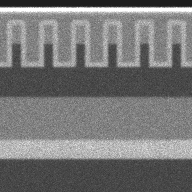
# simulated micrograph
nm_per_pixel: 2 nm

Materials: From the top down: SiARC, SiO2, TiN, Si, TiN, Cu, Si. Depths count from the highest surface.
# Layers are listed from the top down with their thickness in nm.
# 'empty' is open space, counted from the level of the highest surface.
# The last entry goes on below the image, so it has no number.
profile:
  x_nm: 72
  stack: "SiARC 108, SiO2 10, Si 60, TiN 86, Cu 38, Si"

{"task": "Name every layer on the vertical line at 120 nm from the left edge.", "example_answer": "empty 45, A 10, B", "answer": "SiARC 108, SiO2 10, Si 60, TiN 86, Cu 38, Si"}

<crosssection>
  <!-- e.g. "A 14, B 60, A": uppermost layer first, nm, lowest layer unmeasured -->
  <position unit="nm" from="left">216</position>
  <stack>SiARC 24, SiO2 10, TiN 38, Si 106, TiN 86, Cu 38, Si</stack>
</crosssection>